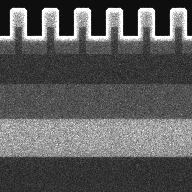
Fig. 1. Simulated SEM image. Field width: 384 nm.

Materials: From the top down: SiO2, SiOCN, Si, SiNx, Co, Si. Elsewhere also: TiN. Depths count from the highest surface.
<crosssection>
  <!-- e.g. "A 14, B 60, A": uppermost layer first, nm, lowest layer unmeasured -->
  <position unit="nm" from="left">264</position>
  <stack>empty 56, SiO2 10, SiOCN 26, Si 60, SiNx 70, Co 76, Si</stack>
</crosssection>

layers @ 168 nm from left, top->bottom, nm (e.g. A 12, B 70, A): SiO2 10, TiN 28, Si 114, SiNx 70, Co 76, Si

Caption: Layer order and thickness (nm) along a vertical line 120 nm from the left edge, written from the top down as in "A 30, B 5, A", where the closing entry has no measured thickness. empty 56, SiO2 10, SiOCN 26, Si 60, SiNx 70, Co 76, Si